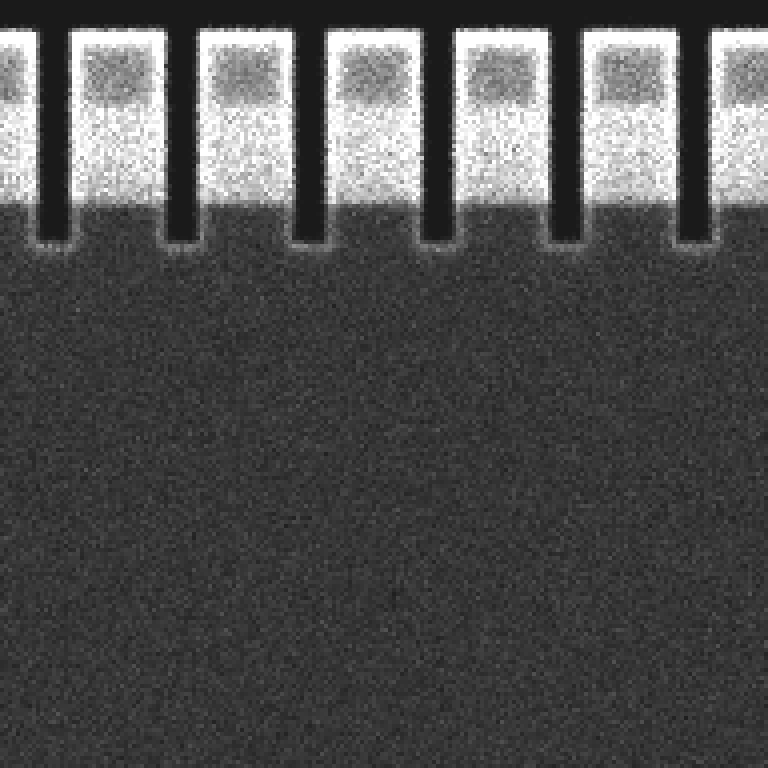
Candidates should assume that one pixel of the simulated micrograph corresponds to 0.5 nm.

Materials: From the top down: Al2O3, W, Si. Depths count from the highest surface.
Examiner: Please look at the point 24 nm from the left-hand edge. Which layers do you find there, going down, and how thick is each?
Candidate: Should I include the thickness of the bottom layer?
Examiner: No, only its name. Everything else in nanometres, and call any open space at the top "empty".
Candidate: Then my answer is empty 106, Si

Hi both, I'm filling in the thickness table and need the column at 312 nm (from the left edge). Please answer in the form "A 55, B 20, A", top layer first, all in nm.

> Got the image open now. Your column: Al2O3 36, W 50, Si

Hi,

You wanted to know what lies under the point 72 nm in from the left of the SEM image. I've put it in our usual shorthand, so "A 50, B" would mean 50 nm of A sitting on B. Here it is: Al2O3 36, W 50, Si